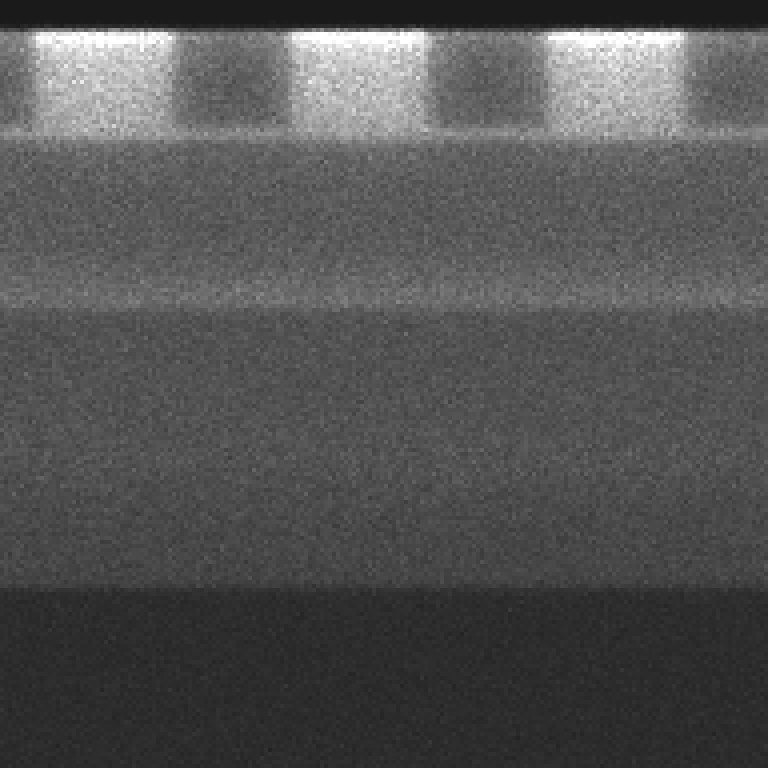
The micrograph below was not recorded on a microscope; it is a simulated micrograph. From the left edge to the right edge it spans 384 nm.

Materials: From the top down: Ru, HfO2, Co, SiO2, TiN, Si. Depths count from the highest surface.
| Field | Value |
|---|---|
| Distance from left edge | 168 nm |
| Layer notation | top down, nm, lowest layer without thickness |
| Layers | HfO2 54, Co 84, SiO2 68, TiN 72, Si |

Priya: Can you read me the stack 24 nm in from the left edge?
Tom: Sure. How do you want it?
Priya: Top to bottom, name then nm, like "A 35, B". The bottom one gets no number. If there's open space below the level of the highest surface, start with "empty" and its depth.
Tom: HfO2 54, Co 84, SiO2 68, TiN 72, Si